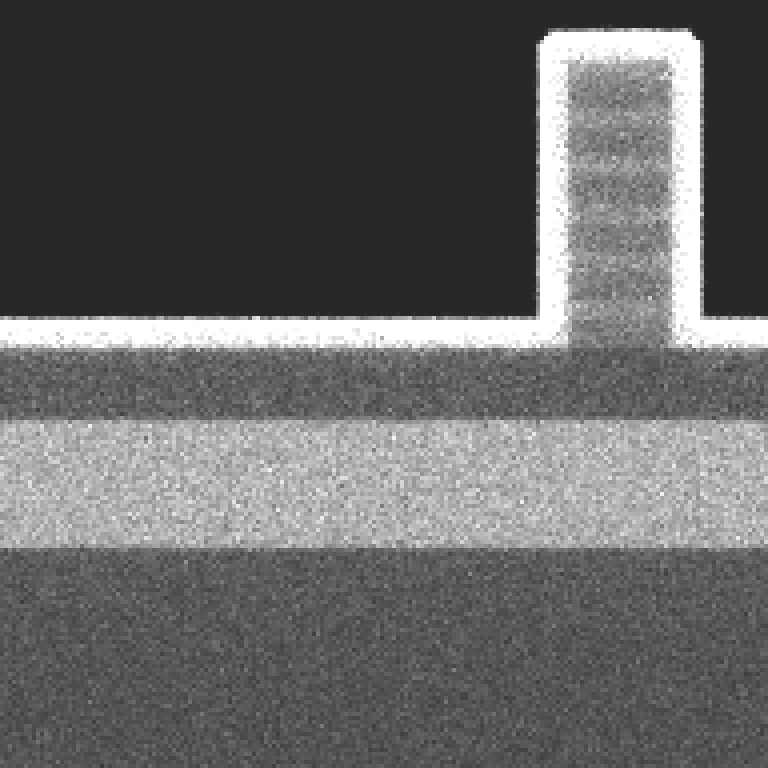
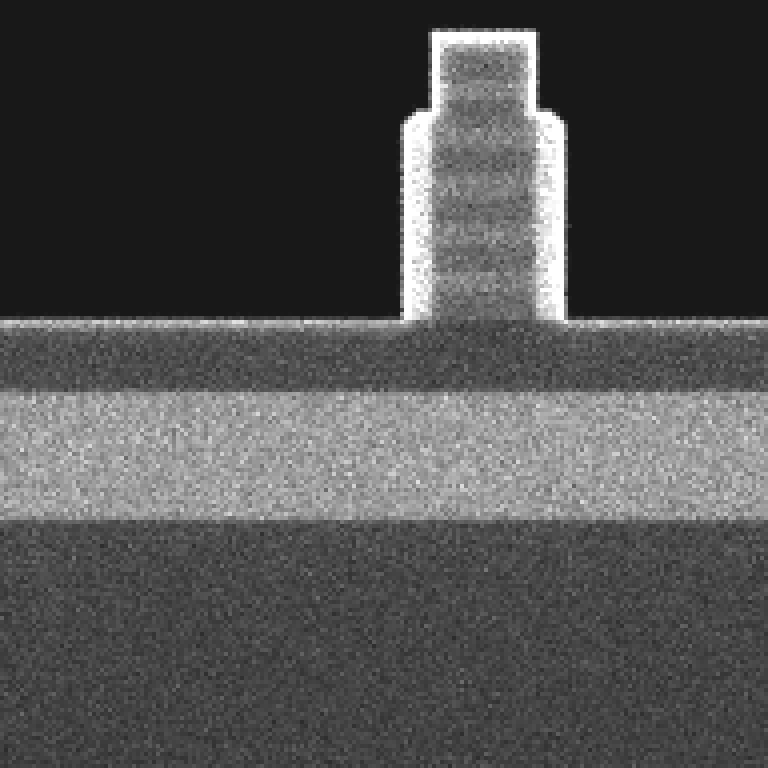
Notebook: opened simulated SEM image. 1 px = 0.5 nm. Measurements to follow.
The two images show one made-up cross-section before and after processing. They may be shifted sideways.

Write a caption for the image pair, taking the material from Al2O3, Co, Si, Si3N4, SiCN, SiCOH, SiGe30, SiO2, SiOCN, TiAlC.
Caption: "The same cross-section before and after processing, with Co removed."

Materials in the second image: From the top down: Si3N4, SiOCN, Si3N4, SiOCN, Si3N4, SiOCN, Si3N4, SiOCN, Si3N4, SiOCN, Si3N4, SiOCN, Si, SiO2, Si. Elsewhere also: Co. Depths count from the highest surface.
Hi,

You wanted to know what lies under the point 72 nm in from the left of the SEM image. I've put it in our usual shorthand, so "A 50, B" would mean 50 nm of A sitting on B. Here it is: empty 144, Si 36, SiO2 64, Si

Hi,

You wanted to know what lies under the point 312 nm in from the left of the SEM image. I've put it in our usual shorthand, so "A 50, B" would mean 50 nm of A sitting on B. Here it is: empty 144, Si 36, SiO2 64, Si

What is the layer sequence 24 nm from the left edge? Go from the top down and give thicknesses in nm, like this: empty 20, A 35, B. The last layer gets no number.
empty 144, Si 36, SiO2 64, Si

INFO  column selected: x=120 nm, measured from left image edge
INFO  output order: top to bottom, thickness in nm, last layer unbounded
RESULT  empty 144, Si 36, SiO2 64, Si